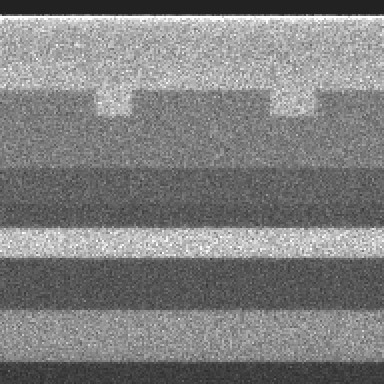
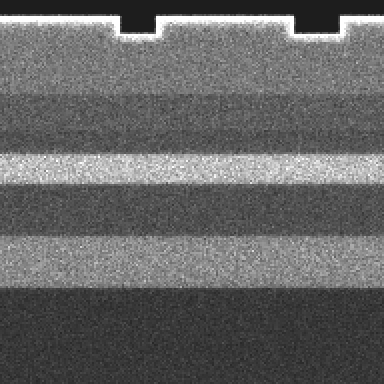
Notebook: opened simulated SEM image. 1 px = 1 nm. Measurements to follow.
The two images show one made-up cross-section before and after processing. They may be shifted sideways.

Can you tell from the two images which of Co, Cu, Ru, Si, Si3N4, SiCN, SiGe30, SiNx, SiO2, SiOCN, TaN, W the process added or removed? Yes, it removed Ru.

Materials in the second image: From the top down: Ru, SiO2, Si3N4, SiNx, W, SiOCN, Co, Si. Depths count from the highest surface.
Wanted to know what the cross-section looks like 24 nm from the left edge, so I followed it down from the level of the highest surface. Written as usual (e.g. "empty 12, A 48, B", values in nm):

SiO2 78, Si3N4 36, SiNx 24, W 30, SiOCN 52, Co 52, Si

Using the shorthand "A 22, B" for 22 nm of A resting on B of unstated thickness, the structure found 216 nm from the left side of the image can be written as SiO2 78, Si3N4 36, SiNx 24, W 30, SiOCN 52, Co 52, Si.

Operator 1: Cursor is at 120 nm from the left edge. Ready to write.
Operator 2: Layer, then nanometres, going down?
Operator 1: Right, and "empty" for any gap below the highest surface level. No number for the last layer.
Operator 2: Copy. empty 18, Ru 8, SiO2 52, Si3N4 36, SiNx 24, W 30, SiOCN 52, Co 52, Si